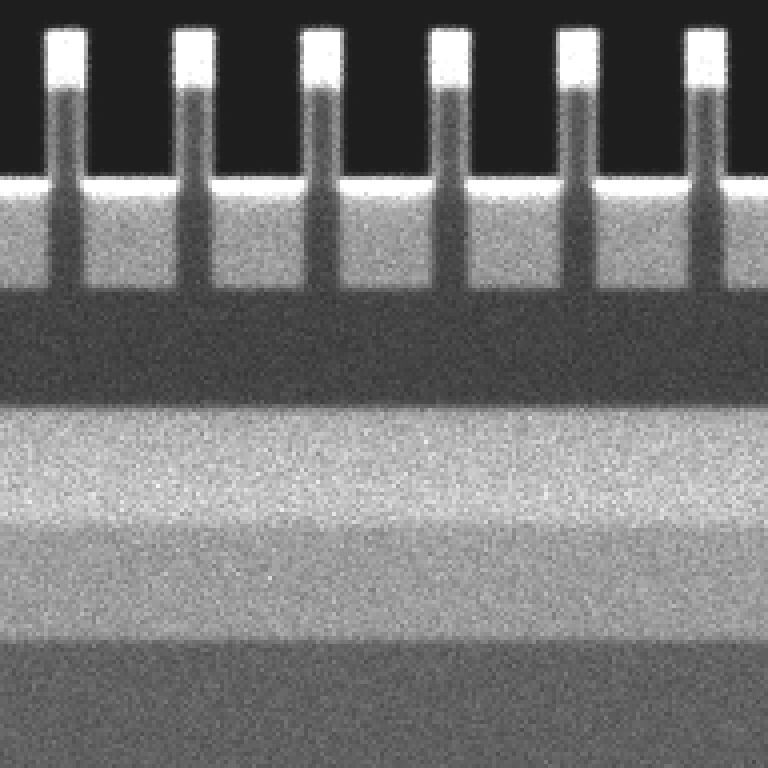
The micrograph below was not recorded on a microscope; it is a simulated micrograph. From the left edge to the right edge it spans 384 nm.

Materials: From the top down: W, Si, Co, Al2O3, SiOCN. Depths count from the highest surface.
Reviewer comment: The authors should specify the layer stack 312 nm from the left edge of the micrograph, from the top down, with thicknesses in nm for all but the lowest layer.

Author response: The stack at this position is empty 74, Al2O3 54, Si 60, Co 58, Al2O3 58, SiOCN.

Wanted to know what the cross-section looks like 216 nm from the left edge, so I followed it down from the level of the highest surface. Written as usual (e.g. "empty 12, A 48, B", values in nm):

W 28, Si 160, Co 58, Al2O3 58, SiOCN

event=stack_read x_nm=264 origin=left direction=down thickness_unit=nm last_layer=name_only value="empty 74, Al2O3 54, Si 60, Co 58, Al2O3 58, SiOCN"